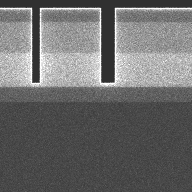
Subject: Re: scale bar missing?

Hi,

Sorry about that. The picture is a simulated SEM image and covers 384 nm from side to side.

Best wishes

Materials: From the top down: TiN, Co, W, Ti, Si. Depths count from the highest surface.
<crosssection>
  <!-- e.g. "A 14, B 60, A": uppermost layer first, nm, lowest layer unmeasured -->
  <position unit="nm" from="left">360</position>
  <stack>TiN 28, Co 62, W 68, Ti 30, Si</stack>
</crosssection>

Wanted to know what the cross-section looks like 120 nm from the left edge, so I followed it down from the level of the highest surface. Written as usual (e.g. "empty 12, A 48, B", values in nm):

TiN 28, Co 62, W 68, Ti 30, Si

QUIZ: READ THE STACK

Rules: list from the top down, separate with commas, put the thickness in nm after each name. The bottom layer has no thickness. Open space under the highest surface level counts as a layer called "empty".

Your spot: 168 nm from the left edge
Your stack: TiN 28, Co 62, W 68, Ti 30, Si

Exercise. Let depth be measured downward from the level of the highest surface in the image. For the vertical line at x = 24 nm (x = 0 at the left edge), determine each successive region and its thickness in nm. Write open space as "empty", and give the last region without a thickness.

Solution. TiN 28, Co 62, W 68, Ti 30, Si